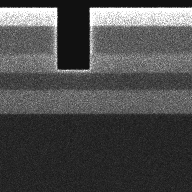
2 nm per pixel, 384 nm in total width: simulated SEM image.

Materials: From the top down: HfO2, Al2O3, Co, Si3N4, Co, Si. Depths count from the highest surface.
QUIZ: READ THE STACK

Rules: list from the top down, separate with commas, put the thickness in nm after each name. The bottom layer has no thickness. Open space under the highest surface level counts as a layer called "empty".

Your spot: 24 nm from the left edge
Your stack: HfO2 36, Al2O3 56, Co 38, Si3N4 34, Co 48, Si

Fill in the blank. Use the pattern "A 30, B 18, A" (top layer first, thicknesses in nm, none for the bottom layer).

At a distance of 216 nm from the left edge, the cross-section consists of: HfO2 36, Al2O3 56, Co 38, Si3N4 34, Co 48, Si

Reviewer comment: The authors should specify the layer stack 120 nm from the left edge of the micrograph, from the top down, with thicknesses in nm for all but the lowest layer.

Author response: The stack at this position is empty 124, Co 6, Si3N4 34, Co 48, Si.